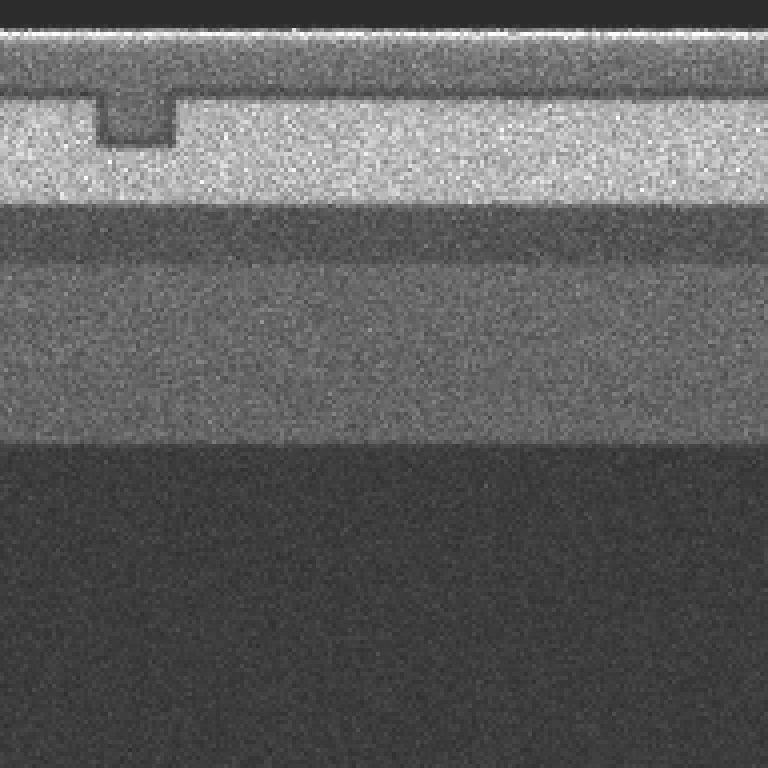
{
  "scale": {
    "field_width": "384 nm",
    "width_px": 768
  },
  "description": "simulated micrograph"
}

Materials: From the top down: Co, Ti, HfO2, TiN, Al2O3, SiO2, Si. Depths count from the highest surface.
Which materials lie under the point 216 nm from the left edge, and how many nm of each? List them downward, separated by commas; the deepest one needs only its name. Co 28, Ti 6, HfO2 52, TiN 30, Al2O3 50, SiO2 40, Si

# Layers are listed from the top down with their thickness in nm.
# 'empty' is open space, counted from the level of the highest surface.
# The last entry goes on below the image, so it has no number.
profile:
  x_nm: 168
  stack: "Co 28, Ti 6, HfO2 52, TiN 30, Al2O3 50, SiO2 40, Si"